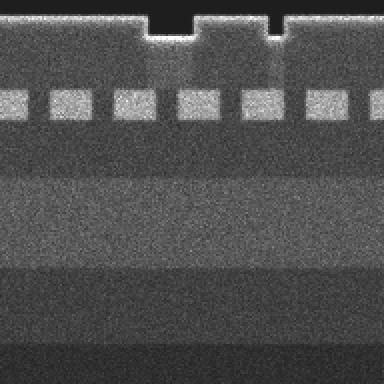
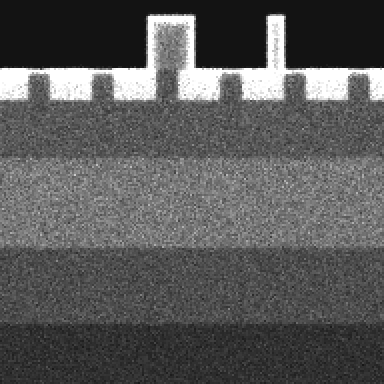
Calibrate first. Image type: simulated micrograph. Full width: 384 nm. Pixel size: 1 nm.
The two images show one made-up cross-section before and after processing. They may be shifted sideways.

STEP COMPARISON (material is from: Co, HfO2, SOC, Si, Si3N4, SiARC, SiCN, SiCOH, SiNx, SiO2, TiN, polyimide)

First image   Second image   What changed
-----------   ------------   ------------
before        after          SOC, removed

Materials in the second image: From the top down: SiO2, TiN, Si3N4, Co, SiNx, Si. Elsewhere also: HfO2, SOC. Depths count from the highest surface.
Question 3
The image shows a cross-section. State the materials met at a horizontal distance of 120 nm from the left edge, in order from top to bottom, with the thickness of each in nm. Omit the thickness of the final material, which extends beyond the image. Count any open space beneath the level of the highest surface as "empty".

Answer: empty 54, HfO2 30, Si3N4 58, Co 90, SiNx 76, Si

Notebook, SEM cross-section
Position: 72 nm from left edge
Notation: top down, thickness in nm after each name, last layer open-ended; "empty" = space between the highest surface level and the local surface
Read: empty 54, HfO2 30, Si3N4 58, Co 90, SiNx 76, Si